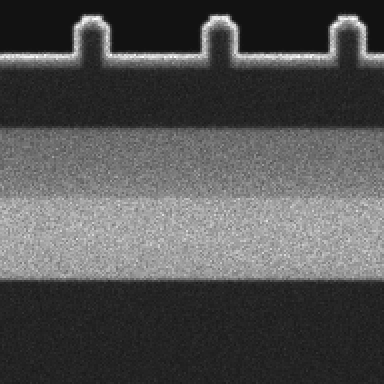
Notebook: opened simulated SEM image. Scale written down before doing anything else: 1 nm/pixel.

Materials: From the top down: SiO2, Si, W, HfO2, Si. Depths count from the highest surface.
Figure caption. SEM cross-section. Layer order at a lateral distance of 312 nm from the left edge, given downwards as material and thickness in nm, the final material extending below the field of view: empty 38, SiO2 14, Si 60, W 70, HfO2 82, Si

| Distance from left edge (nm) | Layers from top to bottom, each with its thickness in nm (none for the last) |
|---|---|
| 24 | empty 38, SiO2 14, Si 60, W 70, HfO2 82, Si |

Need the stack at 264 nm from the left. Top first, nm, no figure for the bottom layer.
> empty 38, SiO2 14, Si 60, W 70, HfO2 82, Si